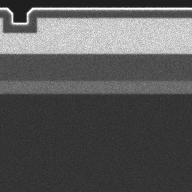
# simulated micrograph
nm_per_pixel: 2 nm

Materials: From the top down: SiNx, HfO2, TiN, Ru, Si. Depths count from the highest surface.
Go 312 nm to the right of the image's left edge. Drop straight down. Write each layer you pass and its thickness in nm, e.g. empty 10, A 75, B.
SiNx 20, HfO2 72, TiN 54, Ru 26, Si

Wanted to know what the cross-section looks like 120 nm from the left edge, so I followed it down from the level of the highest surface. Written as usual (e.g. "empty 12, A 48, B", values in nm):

SiNx 20, HfO2 72, TiN 54, Ru 26, Si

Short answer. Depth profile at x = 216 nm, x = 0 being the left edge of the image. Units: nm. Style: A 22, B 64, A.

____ SiNx 20, HfO2 72, TiN 54, Ru 26, Si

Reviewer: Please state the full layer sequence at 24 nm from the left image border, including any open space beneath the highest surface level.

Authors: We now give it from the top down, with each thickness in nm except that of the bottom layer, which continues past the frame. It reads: empty 10, SiNx 40, HfO2 42, TiN 54, Ru 26, Si